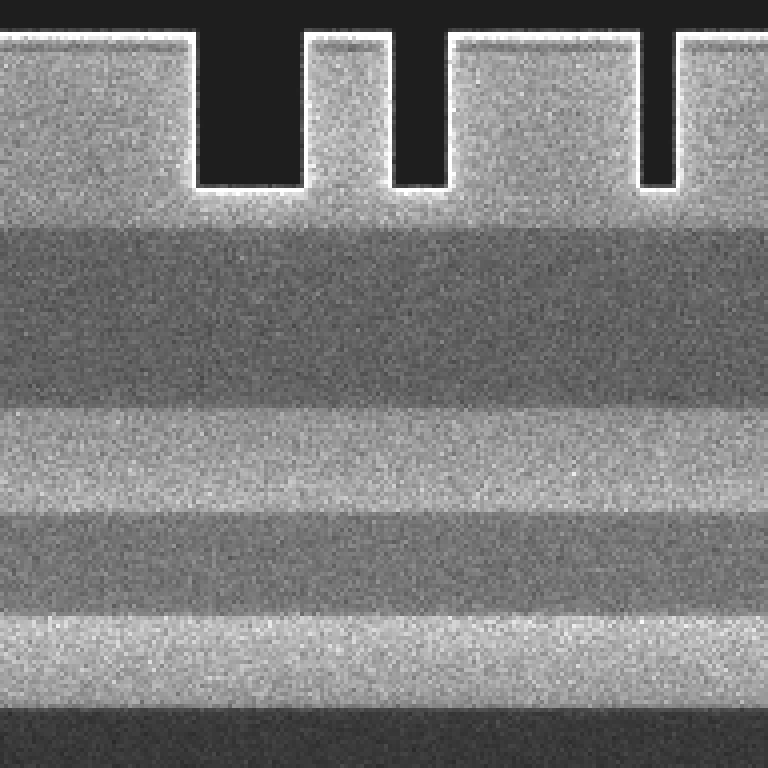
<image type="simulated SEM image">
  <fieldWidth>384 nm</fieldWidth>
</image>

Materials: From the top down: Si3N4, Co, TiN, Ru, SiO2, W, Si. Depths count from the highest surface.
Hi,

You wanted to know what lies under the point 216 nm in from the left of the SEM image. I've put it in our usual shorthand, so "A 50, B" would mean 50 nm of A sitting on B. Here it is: empty 78, Co 20, TiN 90, Ru 52, SiO2 52, W 46, Si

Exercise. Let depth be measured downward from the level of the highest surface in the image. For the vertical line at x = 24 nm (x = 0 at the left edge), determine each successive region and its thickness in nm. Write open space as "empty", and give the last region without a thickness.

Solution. Si3N4 10, Co 88, TiN 90, Ru 52, SiO2 52, W 46, Si